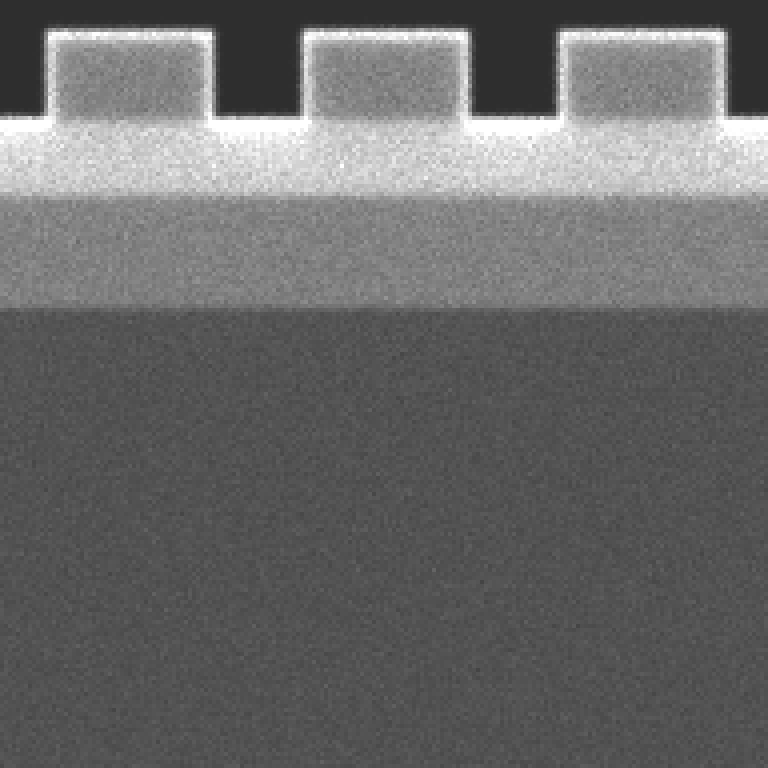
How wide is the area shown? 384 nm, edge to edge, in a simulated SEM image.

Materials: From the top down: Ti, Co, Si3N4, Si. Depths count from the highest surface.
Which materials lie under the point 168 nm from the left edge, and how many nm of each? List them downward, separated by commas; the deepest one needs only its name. Ti 44, Co 38, Si3N4 56, Si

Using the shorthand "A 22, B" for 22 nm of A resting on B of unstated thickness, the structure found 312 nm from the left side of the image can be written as Ti 44, Co 38, Si3N4 56, Si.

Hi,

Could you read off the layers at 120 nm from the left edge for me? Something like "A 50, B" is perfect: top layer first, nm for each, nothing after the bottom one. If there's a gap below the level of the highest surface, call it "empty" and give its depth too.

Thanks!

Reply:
empty 44, Co 38, Si3N4 56, Si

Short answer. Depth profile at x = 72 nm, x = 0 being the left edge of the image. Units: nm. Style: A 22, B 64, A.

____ Ti 44, Co 38, Si3N4 56, Si